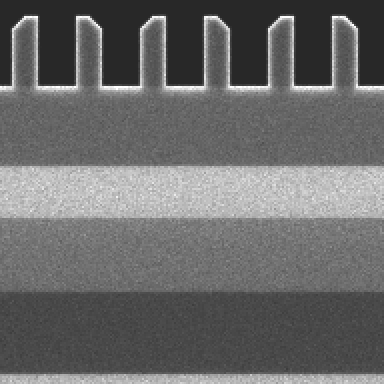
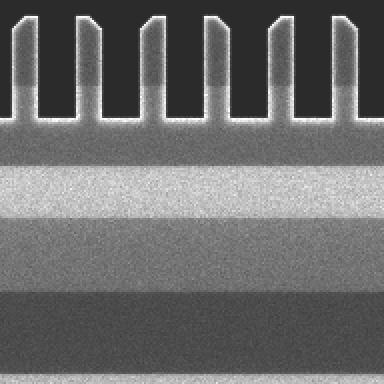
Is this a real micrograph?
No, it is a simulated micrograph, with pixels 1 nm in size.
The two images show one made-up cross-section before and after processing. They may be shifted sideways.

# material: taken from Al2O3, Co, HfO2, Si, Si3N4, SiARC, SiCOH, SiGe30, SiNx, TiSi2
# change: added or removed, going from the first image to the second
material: Al2O3
change: removed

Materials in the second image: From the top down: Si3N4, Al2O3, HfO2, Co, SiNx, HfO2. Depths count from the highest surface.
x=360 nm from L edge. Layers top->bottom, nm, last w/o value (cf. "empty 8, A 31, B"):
empty 102, Al2O3 48, HfO2 52, Co 74, SiNx 82, HfO2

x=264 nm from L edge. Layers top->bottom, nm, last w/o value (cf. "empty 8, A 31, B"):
empty 102, Al2O3 48, HfO2 52, Co 74, SiNx 82, HfO2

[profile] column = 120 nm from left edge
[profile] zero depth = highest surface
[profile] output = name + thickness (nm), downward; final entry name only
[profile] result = empty 102, Al2O3 48, HfO2 52, Co 74, SiNx 82, HfO2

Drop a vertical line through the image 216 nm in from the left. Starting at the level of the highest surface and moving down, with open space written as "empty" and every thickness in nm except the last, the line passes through Si3N4 70, Al2O3 80, HfO2 52, Co 74, SiNx 82, HfO2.